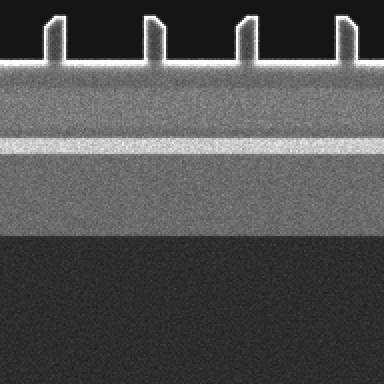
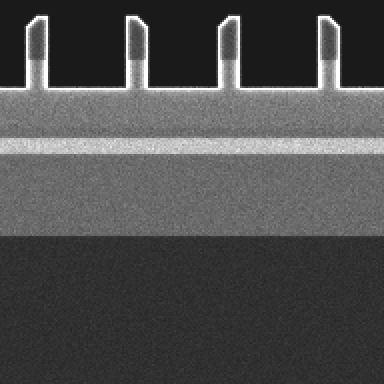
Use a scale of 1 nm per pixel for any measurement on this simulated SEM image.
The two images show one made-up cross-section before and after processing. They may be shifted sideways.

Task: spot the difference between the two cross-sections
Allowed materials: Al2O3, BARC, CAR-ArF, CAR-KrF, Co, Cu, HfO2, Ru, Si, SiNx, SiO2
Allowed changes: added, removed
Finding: removed SiO2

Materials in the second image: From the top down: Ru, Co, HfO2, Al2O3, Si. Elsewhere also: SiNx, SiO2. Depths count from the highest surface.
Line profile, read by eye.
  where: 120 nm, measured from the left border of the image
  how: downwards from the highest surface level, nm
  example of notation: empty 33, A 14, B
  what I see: empty 72, Ru 40, Co 10, HfO2 16, Al2O3 82, Si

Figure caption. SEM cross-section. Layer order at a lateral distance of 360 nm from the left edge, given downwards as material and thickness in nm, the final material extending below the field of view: empty 72, Ru 40, Co 10, HfO2 16, Al2O3 82, Si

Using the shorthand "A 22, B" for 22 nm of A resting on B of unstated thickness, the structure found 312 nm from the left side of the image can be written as empty 72, Ru 40, Co 10, HfO2 16, Al2O3 82, Si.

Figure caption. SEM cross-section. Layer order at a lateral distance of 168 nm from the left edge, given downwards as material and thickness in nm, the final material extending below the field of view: empty 72, Ru 40, Co 10, HfO2 16, Al2O3 82, Si